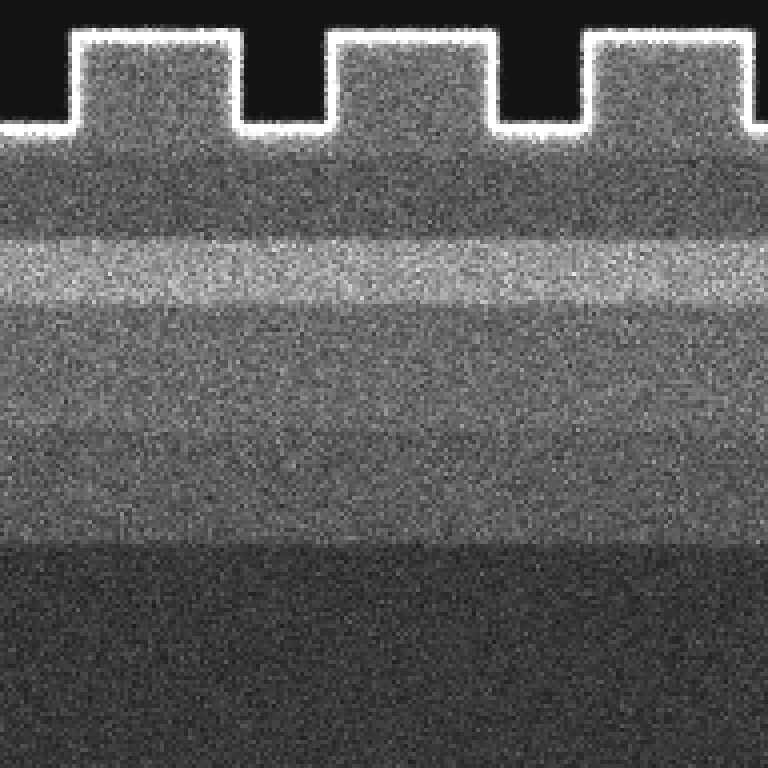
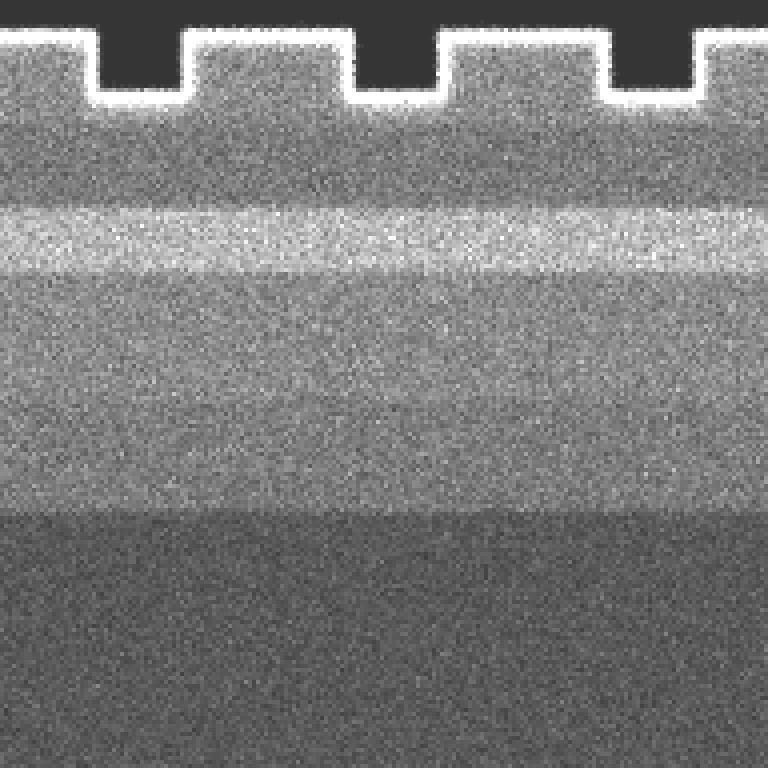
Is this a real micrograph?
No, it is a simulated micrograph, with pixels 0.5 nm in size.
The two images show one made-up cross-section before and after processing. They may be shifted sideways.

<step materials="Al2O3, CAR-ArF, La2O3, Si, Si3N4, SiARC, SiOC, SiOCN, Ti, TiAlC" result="removed Si3N4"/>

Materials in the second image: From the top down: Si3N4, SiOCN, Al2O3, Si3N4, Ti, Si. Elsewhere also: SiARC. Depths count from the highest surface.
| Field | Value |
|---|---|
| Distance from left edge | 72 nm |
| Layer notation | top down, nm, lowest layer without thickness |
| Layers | empty 30, SiARC 16, SiOCN 42, Al2O3 32, Si3N4 64, Ti 56, Si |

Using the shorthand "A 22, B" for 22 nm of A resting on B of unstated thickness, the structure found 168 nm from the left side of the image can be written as Si3N4 46, SiOCN 42, Al2O3 32, Si3N4 64, Ti 56, Si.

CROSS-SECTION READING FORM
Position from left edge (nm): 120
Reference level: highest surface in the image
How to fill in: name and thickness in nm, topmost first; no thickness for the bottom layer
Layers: Si3N4 46, SiOCN 42, Al2O3 32, Si3N4 64, Ti 56, Si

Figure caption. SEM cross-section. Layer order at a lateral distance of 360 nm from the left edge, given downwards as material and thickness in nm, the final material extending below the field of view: Si3N4 46, SiOCN 42, Al2O3 32, Si3N4 64, Ti 56, Si